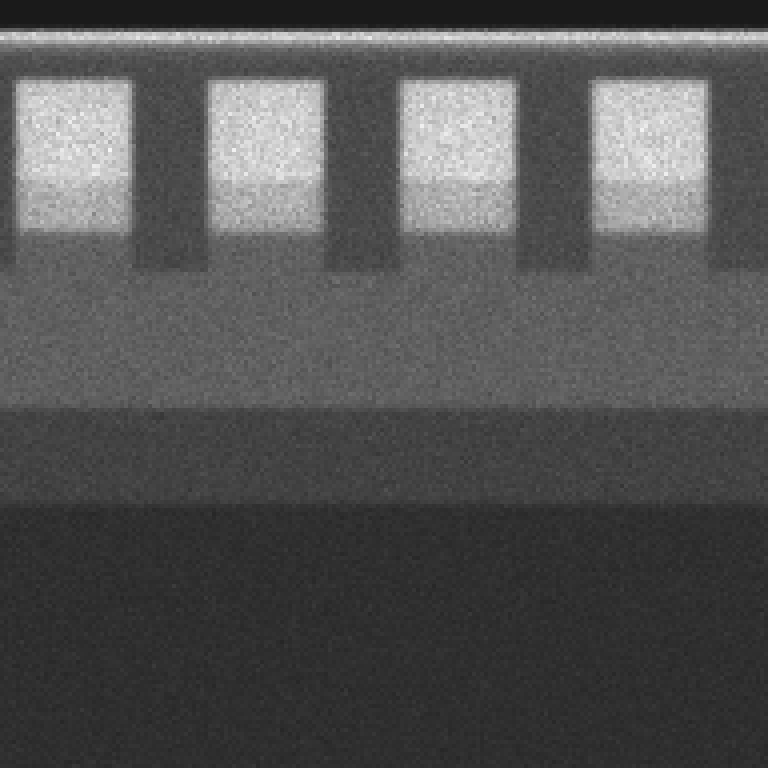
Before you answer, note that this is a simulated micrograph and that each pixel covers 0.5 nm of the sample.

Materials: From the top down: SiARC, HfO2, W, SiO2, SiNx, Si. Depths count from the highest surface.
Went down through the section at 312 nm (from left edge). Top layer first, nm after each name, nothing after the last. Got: SiARC 24, HfO2 50, W 26, SiO2 88, SiNx 48, Si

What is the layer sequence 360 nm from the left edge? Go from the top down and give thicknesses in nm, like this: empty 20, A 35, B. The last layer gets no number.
SiARC 120, SiO2 68, SiNx 48, Si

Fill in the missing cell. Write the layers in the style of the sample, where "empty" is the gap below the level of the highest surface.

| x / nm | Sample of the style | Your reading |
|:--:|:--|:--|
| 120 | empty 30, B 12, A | SiARC 24, HfO2 50, W 26, SiO2 88, SiNx 48, Si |